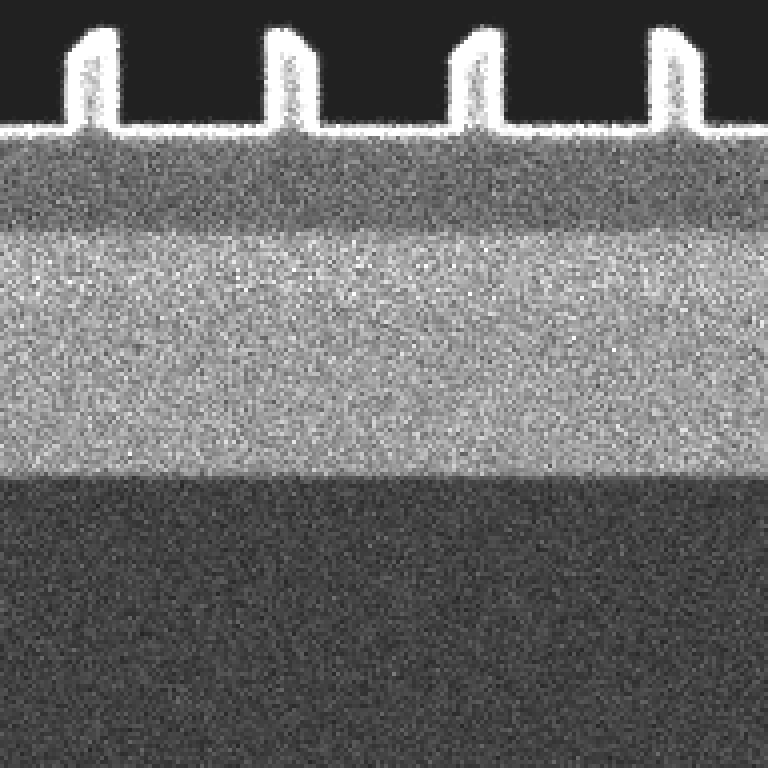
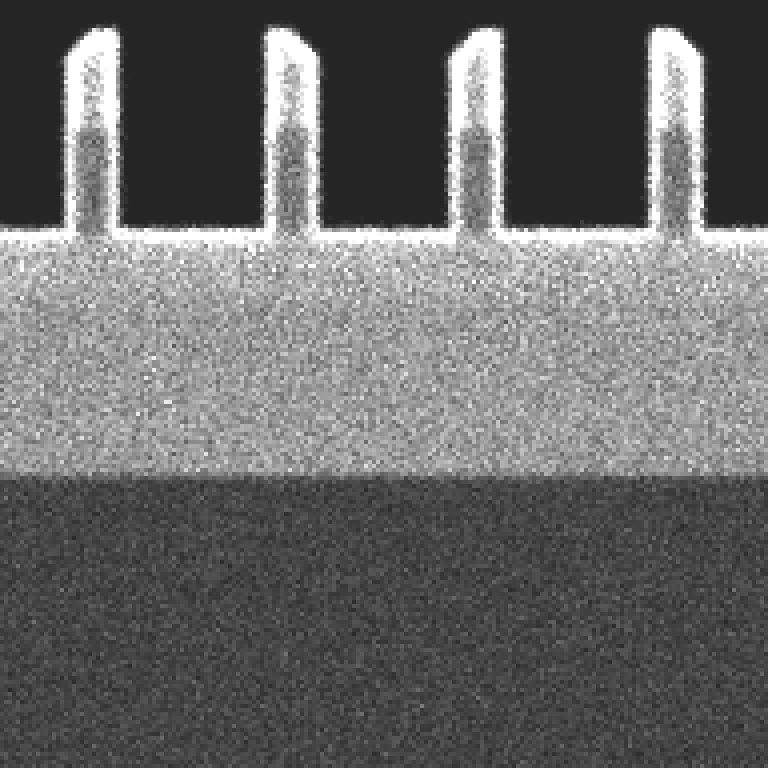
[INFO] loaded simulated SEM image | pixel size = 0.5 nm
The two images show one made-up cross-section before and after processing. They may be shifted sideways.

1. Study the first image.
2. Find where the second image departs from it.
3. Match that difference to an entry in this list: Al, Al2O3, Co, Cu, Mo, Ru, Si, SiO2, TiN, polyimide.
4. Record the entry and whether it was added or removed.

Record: TiN / removed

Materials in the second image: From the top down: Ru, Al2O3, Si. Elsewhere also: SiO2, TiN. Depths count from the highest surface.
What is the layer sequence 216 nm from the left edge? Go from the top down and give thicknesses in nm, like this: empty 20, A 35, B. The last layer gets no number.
empty 100, Ru 34, Al2O3 88, Si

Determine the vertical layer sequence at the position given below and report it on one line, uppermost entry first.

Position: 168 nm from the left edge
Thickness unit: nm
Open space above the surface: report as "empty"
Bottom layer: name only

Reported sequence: empty 100, Ru 34, Al2O3 88, Si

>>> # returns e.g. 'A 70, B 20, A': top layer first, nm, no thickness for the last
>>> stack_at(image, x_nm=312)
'empty 100, Ru 34, Al2O3 88, Si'